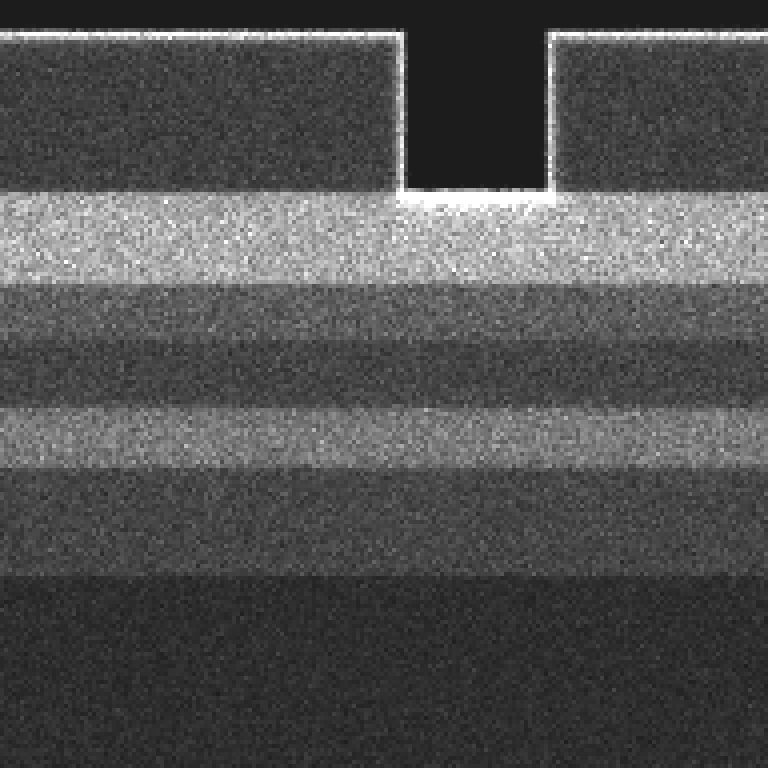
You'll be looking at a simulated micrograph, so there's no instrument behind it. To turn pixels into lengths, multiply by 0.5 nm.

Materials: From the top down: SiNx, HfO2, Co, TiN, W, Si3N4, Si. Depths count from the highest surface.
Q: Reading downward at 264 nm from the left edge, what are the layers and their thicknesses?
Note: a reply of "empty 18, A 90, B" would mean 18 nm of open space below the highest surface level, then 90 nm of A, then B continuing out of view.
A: empty 80, HfO2 46, Co 28, TiN 34, W 30, Si3N4 54, Si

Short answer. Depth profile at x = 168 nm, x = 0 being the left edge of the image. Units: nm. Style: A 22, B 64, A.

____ SiNx 80, HfO2 46, Co 28, TiN 34, W 30, Si3N4 54, Si